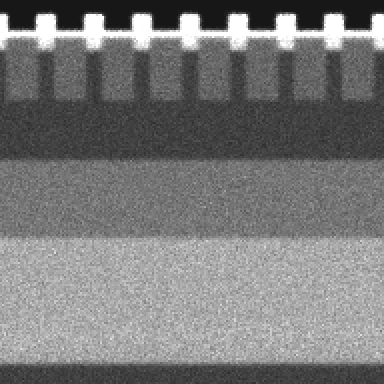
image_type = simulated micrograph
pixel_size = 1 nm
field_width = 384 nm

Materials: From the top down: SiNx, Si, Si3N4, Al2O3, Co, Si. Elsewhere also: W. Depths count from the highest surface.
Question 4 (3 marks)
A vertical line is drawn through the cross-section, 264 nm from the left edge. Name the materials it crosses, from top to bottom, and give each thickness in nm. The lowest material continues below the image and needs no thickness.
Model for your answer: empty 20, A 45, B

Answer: empty 16, SiNx 68, Si 60, Si3N4 78, Al2O3 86, Co 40, Si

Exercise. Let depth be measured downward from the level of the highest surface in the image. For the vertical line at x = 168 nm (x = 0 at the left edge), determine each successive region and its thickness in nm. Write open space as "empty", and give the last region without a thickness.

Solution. empty 16, SiNx 68, Si 60, Si3N4 78, Al2O3 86, Co 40, Si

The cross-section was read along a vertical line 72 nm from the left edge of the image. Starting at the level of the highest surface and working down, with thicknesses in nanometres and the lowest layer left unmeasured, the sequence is empty 16, SiNx 68, Si 60, Si3N4 78, Al2O3 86, Co 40, Si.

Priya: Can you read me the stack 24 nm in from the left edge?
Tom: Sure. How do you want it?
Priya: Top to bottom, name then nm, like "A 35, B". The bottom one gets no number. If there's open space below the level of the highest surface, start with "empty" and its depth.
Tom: empty 16, SiNx 68, Si 60, Si3N4 78, Al2O3 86, Co 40, Si